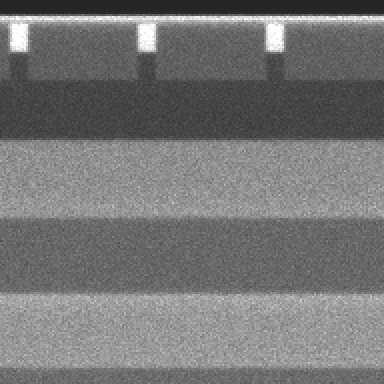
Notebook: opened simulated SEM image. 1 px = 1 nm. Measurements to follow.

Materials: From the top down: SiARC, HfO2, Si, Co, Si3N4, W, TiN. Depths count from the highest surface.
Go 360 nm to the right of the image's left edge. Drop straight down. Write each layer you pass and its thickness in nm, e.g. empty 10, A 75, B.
SiARC 64, Si 60, Co 78, Si3N4 76, W 74, TiN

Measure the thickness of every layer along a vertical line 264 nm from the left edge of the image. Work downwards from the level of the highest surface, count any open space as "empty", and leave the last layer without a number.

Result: SiARC 64, Si 60, Co 78, Si3N4 76, W 74, TiN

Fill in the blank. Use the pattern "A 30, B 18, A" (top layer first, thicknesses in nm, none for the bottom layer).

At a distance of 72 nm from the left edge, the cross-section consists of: SiARC 64, Si 60, Co 78, Si3N4 76, W 74, TiN